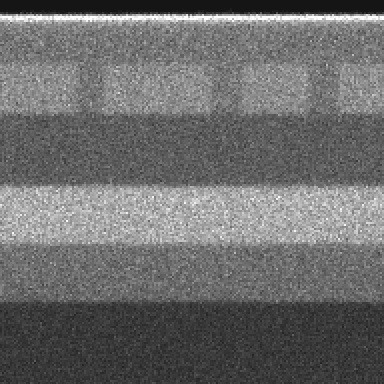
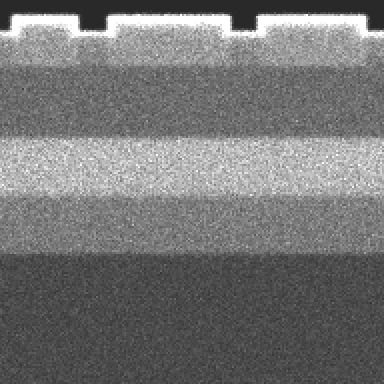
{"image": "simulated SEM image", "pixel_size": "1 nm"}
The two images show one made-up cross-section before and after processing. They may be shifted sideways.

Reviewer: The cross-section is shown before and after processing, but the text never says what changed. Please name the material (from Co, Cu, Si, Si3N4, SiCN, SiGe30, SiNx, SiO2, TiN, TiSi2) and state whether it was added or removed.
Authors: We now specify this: TiN, removed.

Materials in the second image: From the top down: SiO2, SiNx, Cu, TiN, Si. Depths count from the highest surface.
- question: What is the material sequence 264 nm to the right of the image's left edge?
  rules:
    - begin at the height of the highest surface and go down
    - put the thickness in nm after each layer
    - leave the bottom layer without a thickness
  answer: SiO2 50, SiNx 72, Cu 58, TiN 58, Si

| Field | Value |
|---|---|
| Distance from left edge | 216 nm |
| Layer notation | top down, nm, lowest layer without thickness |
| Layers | SiO2 50, SiNx 72, Cu 58, TiN 58, Si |